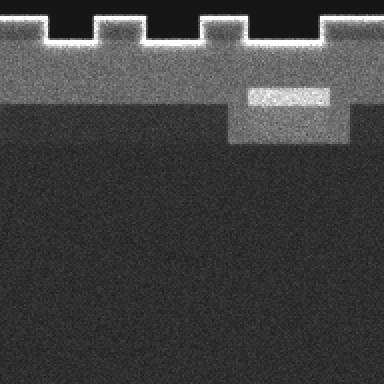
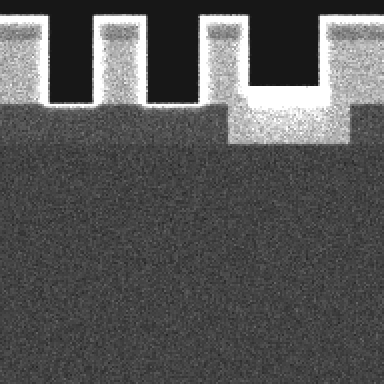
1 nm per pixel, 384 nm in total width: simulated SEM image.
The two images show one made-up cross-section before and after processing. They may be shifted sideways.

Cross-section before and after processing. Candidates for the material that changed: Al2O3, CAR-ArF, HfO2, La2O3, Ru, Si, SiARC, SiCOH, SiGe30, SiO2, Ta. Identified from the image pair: SiO2 (removed).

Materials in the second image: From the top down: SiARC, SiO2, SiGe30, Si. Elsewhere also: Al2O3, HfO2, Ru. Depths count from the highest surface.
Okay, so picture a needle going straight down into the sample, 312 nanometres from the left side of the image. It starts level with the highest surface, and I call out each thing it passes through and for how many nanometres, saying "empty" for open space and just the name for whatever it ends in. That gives empty 72, HfO2 18, Ru 38, Si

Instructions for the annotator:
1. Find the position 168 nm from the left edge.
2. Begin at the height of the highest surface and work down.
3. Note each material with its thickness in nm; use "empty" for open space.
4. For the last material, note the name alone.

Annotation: empty 88, SiGe30 40, Si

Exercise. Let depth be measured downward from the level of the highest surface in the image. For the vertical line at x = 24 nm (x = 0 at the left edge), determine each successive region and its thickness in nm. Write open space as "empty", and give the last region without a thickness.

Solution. SiARC 24, SiO2 64, SiGe30 40, Si